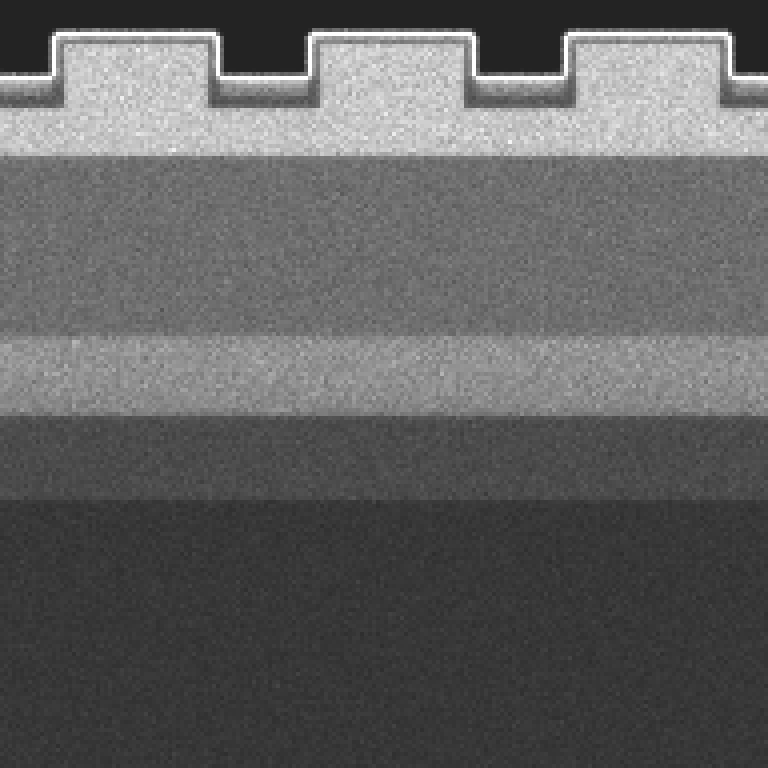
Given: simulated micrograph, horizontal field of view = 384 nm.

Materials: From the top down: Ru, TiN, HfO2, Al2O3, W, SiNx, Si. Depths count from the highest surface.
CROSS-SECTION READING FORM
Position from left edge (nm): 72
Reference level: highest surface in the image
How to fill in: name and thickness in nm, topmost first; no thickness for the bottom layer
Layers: TiN 6, HfO2 56, Al2O3 90, W 40, SiNx 42, Si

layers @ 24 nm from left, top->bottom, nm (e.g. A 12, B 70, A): empty 22, Ru 10, TiN 6, HfO2 24, Al2O3 90, W 40, SiNx 42, Si